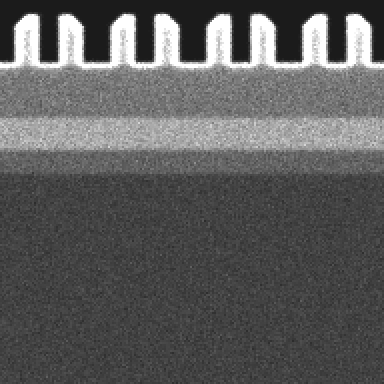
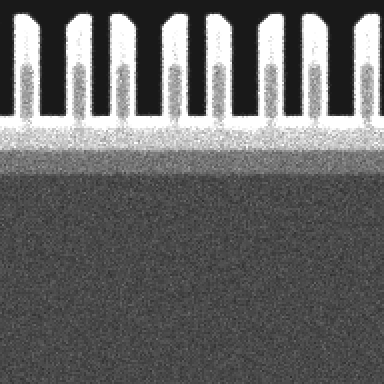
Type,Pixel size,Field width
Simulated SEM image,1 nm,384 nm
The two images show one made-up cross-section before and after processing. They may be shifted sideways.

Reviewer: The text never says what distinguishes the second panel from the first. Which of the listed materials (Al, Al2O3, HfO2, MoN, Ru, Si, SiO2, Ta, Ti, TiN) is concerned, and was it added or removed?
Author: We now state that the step removed TiN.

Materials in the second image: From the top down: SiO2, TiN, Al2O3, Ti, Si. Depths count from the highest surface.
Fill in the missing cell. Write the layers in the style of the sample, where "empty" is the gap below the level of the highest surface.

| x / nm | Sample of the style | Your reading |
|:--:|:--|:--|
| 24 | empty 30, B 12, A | SiO2 48, TiN 54, Al2O3 32, Ti 24, Si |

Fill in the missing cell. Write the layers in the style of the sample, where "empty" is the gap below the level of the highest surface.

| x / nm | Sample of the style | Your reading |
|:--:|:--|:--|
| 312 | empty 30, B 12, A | SiO2 48, TiN 54, Al2O3 32, Ti 24, Si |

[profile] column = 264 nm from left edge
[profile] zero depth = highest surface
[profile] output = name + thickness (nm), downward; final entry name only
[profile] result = empty 6, SiO2 42, TiN 54, Al2O3 32, Ti 24, Si